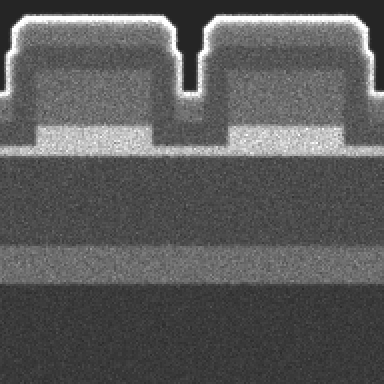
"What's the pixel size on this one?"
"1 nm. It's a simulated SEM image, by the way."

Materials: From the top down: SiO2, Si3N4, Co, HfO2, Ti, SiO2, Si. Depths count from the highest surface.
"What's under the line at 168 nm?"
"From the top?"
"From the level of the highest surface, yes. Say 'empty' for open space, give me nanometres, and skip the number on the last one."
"empty 6, SiO2 30, Si3N4 94, HfO2 10, Ti 90, SiO2 38, Si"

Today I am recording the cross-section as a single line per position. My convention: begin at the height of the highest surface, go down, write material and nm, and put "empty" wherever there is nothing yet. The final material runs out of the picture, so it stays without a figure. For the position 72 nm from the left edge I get SiO2 30, Si3N4 24, Co 56, HfO2 30, Ti 90, SiO2 38, Si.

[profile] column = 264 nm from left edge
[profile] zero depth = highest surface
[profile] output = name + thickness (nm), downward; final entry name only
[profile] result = SiO2 30, Si3N4 24, Co 56, HfO2 30, Ti 90, SiO2 38, Si